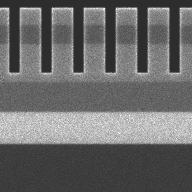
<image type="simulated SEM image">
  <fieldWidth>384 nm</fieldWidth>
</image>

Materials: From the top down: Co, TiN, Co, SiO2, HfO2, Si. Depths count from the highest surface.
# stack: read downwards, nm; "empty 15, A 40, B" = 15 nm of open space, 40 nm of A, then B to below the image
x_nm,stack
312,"Co 34, TiN 38, Co 76, SiO2 60, HfO2 64, Si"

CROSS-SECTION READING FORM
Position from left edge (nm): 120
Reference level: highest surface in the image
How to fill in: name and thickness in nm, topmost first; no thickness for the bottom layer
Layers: Co 34, TiN 38, Co 76, SiO2 60, HfO2 64, Si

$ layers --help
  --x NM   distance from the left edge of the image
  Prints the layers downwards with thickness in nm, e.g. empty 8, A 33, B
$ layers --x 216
empty 130, Co 18, SiO2 60, HfO2 64, Si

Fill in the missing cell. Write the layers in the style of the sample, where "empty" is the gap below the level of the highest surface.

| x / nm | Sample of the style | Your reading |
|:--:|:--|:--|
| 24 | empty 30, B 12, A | empty 130, Co 18, SiO2 60, HfO2 64, Si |